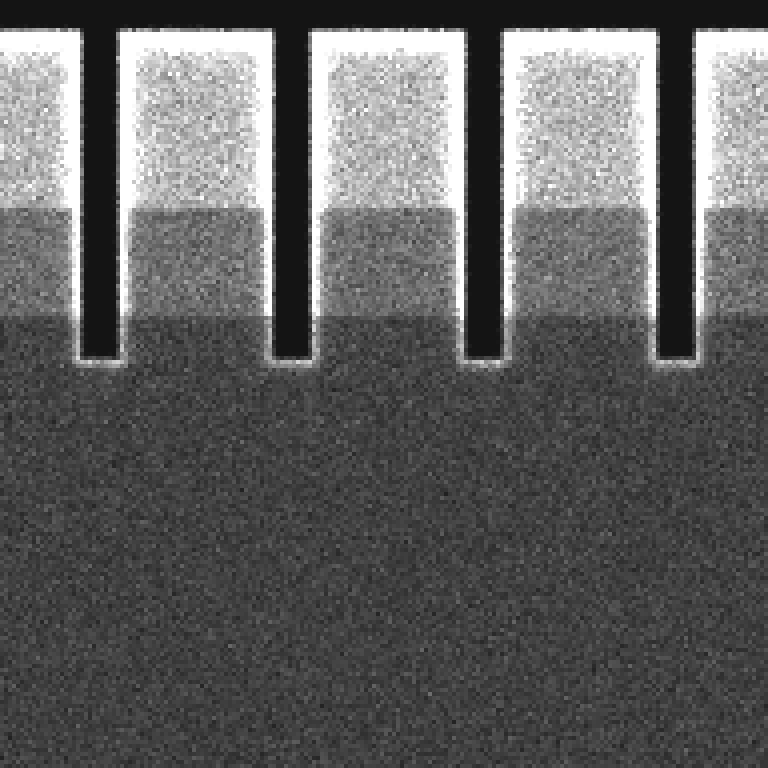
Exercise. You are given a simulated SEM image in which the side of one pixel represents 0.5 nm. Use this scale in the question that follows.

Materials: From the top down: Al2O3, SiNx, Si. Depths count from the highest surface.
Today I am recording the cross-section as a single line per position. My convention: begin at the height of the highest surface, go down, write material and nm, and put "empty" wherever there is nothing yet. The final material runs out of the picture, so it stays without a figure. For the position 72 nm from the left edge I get Al2O3 88, SiNx 54, Si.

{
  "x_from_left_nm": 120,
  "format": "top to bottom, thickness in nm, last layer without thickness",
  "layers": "Al2O3 88, SiNx 54, Si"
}